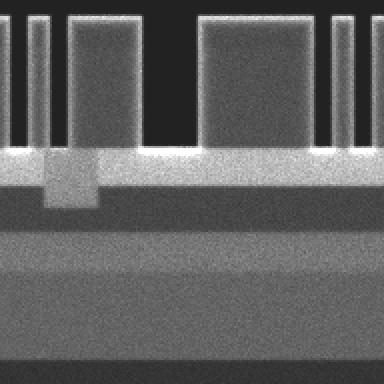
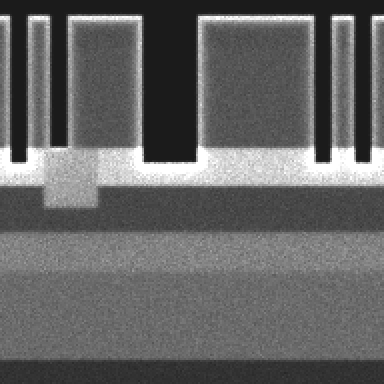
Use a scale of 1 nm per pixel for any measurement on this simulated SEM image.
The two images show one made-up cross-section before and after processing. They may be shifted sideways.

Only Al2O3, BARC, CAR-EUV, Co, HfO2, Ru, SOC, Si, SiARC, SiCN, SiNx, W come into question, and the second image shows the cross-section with HfO2 removed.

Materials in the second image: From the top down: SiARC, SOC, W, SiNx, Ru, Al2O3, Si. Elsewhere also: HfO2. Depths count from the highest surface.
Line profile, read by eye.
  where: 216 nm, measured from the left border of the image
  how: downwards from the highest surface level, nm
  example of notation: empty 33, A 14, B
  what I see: SiARC 32, SOC 100, HfO2 38, SiNx 46, Ru 40, Al2O3 88, Si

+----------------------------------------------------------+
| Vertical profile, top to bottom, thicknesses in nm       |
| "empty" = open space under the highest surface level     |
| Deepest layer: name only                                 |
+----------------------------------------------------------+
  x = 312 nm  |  SiARC 32, SOC 100, HfO2 38, SiNx 46, Ru 40, Al2O3 88, Si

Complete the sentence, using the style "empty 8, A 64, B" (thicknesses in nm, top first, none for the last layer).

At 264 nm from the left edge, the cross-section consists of SiARC 32, SOC 100, HfO2 38, SiNx 46, Ru 40, Al2O3 88, Si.